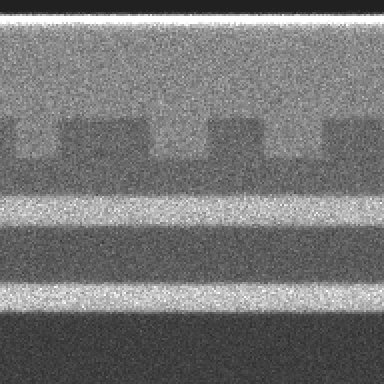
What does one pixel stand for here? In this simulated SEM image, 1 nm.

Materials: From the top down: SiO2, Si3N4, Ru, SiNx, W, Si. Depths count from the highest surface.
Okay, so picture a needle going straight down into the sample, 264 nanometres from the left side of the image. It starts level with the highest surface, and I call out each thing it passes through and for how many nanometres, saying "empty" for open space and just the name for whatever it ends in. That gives SiO2 142, Si3N4 38, Ru 30, SiNx 58, W 28, Si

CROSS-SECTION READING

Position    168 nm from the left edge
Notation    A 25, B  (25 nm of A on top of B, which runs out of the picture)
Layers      SiO2 142, Si3N4 38, Ru 30, SiNx 58, W 28, Si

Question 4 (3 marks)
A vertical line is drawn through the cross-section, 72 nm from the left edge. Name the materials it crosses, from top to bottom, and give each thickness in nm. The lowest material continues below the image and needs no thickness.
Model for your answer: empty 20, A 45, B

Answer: SiO2 102, Si3N4 78, Ru 30, SiNx 58, W 28, Si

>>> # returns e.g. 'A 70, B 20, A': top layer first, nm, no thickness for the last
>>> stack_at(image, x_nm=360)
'SiO2 102, Si3N4 78, Ru 30, SiNx 58, W 28, Si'